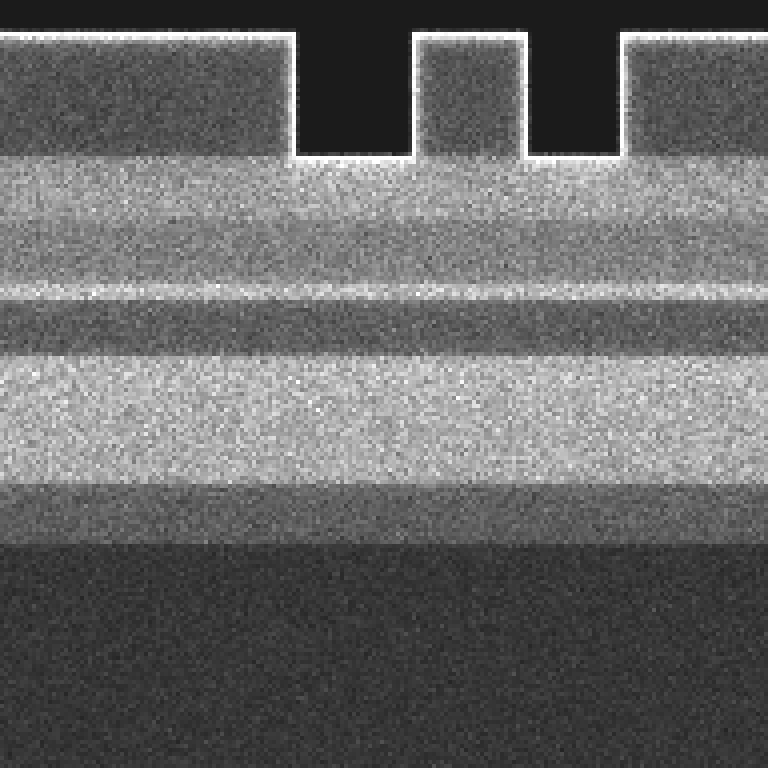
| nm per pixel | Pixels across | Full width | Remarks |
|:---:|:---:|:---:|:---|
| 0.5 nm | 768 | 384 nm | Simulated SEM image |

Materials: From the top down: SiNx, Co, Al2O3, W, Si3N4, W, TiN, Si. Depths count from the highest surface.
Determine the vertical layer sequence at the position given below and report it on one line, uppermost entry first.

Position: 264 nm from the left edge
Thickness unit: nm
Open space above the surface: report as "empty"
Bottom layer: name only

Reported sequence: empty 62, Co 32, Al2O3 32, W 8, Si3N4 28, W 64, TiN 30, Si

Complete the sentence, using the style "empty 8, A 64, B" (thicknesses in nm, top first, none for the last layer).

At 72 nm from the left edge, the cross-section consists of SiNx 62, Co 32, Al2O3 32, W 8, Si3N4 28, W 64, TiN 30, Si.